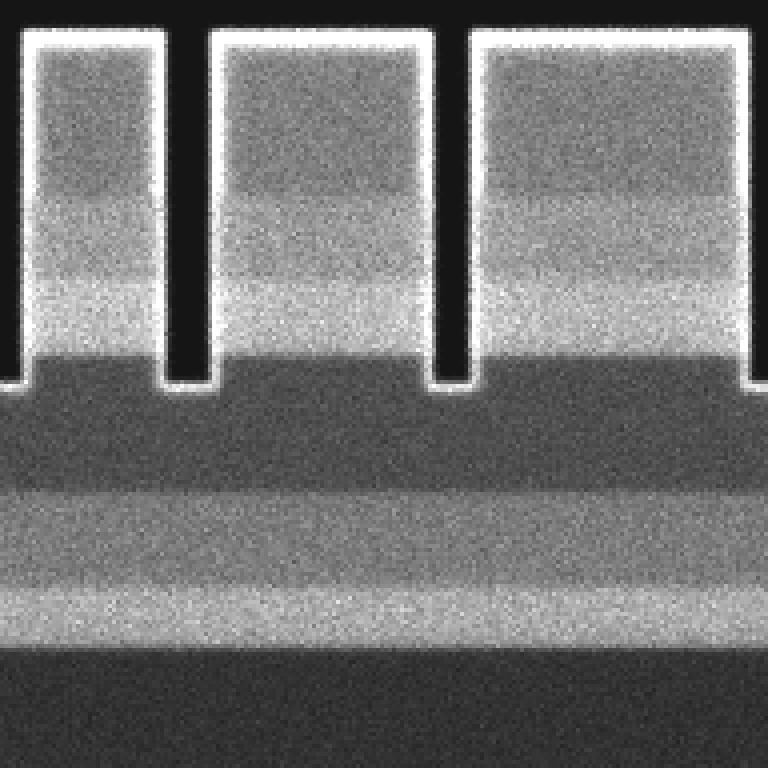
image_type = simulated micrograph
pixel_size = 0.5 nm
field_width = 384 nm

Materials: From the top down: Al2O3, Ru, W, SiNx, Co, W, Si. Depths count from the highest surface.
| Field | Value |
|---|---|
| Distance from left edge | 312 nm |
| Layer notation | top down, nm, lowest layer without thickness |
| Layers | Al2O3 82, Ru 42, W 38, SiNx 68, Co 48, W 30, Si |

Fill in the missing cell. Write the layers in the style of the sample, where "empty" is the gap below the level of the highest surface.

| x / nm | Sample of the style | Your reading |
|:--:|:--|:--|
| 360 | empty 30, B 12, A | Al2O3 82, Ru 42, W 38, SiNx 68, Co 48, W 30, Si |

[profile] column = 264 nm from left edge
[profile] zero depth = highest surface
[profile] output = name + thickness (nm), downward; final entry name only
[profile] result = Al2O3 82, Ru 42, W 38, SiNx 68, Co 48, W 30, Si